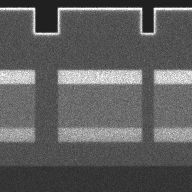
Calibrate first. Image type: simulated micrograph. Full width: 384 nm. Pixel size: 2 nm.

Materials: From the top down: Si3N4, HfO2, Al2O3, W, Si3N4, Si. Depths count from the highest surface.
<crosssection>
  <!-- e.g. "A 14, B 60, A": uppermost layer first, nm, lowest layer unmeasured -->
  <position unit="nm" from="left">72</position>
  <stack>empty 50, Si3N4 266, Si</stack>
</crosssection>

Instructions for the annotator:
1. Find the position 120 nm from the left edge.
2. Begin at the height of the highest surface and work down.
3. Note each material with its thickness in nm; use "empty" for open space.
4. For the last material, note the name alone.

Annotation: Si3N4 124, HfO2 28, Al2O3 88, W 28, Si3N4 48, Si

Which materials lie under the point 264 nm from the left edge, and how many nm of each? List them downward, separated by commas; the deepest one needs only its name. Si3N4 124, HfO2 28, Al2O3 88, W 28, Si3N4 48, Si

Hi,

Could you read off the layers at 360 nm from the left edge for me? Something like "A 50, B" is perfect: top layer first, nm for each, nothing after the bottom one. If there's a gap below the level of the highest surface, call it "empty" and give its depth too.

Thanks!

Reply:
Si3N4 124, HfO2 28, Al2O3 88, W 28, Si3N4 48, Si